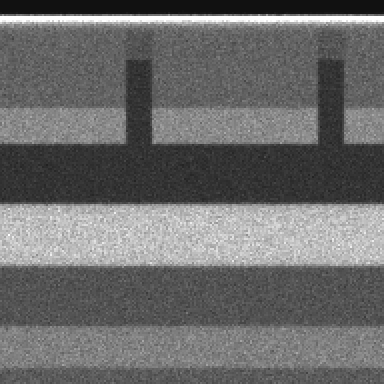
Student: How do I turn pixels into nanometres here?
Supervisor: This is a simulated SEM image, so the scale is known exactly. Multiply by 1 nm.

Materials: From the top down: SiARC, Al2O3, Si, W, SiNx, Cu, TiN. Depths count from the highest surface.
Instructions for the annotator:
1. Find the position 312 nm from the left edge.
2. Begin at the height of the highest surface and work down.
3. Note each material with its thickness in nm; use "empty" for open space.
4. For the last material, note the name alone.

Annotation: SiARC 92, Al2O3 36, Si 60, W 62, SiNx 60, Cu 42, TiN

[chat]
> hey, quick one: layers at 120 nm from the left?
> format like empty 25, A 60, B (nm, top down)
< SiARC 92, Al2O3 36, Si 60, W 62, SiNx 60, Cu 42, TiN